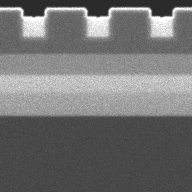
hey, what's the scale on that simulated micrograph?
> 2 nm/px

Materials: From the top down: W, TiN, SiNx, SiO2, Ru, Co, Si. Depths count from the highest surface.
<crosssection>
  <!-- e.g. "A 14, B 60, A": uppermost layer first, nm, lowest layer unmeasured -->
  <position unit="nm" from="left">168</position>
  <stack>TiN 66, SiNx 26, SiO2 42, Ru 36, Co 46, Si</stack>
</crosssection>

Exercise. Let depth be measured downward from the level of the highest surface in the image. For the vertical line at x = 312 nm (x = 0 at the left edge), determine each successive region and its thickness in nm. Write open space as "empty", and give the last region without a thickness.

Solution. empty 18, W 40, TiN 8, SiNx 26, SiO2 42, Ru 36, Co 46, Si